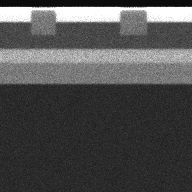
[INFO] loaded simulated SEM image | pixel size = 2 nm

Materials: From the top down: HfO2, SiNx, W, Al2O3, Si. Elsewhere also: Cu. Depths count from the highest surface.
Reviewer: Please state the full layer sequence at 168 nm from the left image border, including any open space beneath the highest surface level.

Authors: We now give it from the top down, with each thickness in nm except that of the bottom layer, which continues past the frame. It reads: HfO2 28, SiNx 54, W 28, Al2O3 42, Si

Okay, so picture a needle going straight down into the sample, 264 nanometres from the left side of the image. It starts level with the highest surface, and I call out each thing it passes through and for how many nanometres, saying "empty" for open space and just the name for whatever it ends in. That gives Cu 54, SiNx 28, W 28, Al2O3 42, Si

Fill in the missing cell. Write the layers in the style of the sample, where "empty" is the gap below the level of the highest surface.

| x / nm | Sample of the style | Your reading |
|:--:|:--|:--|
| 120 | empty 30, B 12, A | HfO2 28, SiNx 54, W 28, Al2O3 42, Si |